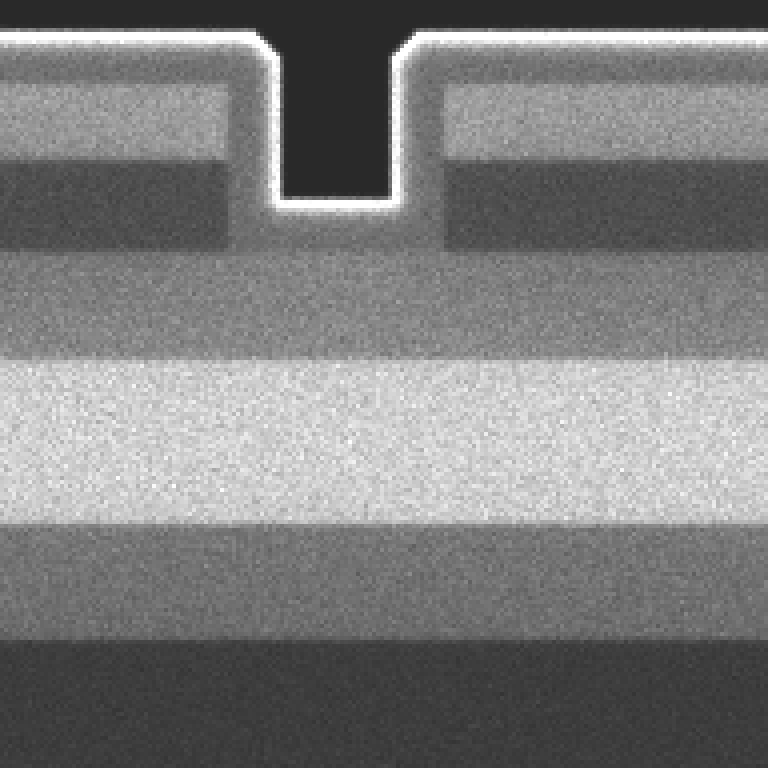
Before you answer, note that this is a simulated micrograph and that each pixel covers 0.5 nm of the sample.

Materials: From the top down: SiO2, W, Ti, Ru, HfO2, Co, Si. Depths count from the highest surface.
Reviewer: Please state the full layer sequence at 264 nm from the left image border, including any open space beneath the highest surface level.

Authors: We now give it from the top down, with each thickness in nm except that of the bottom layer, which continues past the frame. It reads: SiO2 26, W 38, Ti 46, Ru 54, HfO2 82, Co 58, Si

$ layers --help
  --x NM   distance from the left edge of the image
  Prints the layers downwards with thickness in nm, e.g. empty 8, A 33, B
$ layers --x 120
SiO2 110, Ru 54, HfO2 82, Co 58, Si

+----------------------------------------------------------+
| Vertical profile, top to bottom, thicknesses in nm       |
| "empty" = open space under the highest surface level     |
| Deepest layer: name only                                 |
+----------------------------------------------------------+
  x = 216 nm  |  SiO2 110, Ru 54, HfO2 82, Co 58, Si